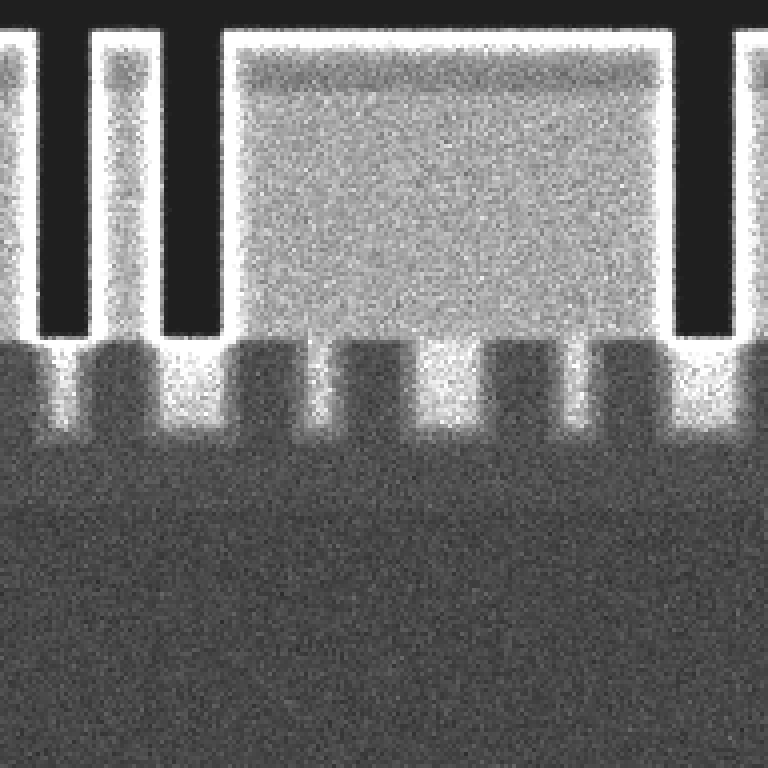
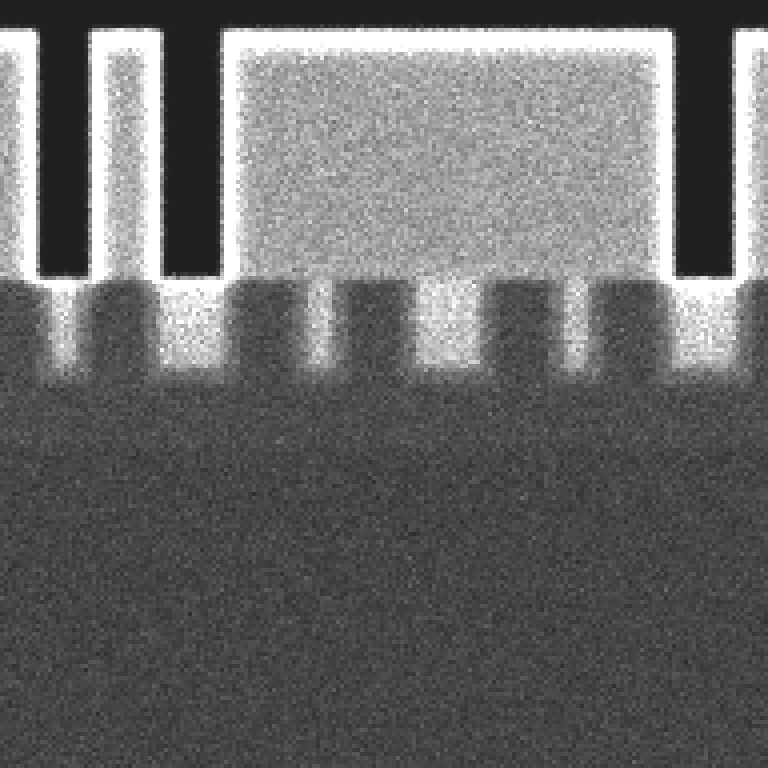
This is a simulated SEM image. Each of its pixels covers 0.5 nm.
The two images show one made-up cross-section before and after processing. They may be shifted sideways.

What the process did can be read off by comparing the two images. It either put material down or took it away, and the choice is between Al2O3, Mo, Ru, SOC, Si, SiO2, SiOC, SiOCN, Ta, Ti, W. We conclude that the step removed SOC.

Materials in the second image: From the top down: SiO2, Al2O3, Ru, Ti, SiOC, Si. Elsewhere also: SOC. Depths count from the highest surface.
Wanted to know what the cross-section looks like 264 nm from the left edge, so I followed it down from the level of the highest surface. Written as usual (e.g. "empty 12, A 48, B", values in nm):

SiO2 114, Al2O3 10, SiOC 84, Si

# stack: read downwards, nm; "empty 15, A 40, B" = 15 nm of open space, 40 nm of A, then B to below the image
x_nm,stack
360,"empty 124, Ru 44, Ti 8, SiOC 32, Si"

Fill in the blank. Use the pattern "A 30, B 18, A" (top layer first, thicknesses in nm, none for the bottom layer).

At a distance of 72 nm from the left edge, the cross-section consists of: SiO2 114, Al2O3 10, Ti 52, SiOC 32, Si